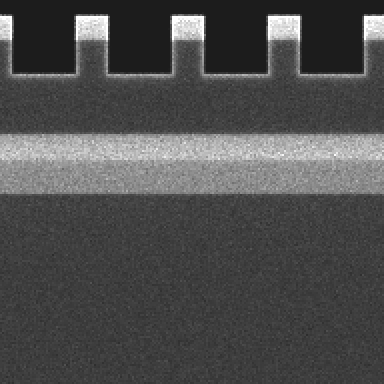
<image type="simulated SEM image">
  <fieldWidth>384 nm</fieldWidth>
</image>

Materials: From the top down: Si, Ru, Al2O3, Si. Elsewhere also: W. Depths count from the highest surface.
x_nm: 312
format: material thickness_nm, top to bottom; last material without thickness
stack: empty 58, Si 60, Ru 26, Al2O3 34, Si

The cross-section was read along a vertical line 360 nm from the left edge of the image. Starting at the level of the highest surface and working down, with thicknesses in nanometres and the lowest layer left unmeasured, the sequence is empty 58, Si 60, Ru 26, Al2O3 34, Si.